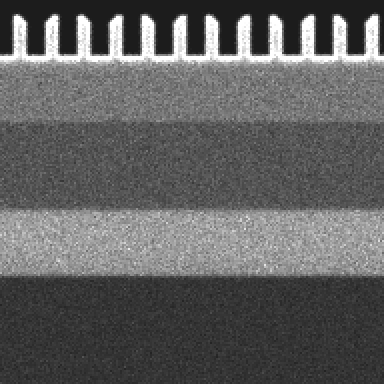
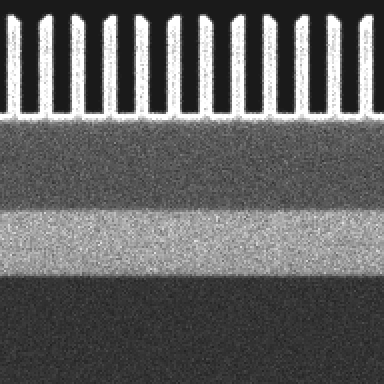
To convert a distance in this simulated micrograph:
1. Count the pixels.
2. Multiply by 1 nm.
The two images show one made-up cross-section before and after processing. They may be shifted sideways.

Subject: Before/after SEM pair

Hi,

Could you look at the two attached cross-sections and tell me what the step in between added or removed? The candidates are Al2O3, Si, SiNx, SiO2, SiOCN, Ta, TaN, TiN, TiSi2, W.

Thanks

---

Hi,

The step removed Al2O3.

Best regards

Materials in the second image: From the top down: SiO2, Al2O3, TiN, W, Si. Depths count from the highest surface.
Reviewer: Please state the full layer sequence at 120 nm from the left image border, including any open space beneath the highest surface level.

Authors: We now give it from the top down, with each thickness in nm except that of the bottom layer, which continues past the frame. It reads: empty 98, Al2O3 8, TiN 88, W 66, Si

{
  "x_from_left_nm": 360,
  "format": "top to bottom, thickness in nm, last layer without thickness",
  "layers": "empty 6, SiO2 34, Al2O3 66, TiN 88, W 66, Si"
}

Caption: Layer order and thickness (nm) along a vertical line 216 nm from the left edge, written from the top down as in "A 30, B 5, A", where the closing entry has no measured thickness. empty 98, Al2O3 8, TiN 88, W 66, Si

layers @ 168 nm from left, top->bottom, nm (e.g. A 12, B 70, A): empty 6, SiO2 34, Al2O3 66, TiN 88, W 66, Si